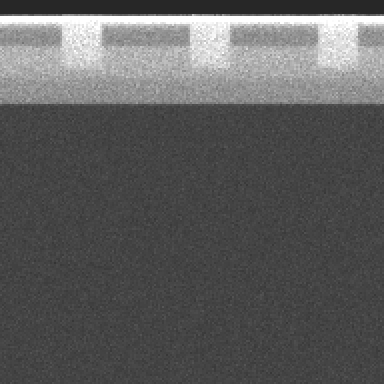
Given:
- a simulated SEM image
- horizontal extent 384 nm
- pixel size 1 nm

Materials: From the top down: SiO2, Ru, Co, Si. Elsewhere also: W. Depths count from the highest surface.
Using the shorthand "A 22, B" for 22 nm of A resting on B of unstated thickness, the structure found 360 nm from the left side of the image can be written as SiO2 30, Ru 32, Co 26, Si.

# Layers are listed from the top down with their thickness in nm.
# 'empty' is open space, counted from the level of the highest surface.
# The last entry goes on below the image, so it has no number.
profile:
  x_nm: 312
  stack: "SiO2 30, Ru 32, Co 26, Si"